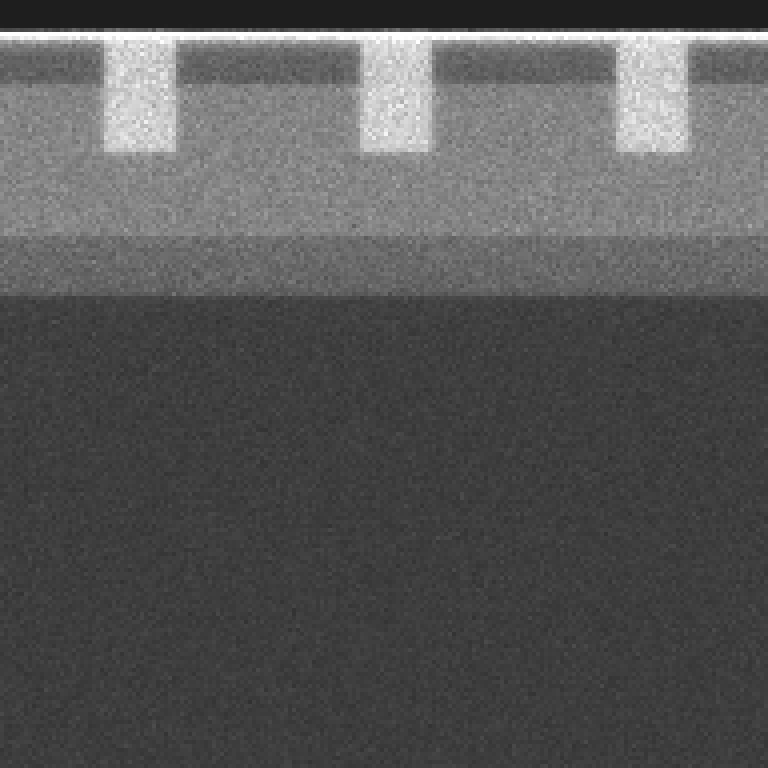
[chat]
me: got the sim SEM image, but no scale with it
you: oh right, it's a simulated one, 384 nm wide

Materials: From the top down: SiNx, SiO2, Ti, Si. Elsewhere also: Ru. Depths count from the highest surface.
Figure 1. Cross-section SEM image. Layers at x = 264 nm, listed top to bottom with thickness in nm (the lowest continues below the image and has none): SiNx 26, SiO2 76, Ti 30, Si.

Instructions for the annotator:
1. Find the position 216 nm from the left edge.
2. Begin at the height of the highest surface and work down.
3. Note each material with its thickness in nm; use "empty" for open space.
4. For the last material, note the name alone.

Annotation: SiNx 26, SiO2 76, Ti 30, Si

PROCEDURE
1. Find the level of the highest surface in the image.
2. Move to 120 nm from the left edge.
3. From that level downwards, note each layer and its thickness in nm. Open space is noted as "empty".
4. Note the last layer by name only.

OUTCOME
SiNx 26, SiO2 76, Ti 30, Si